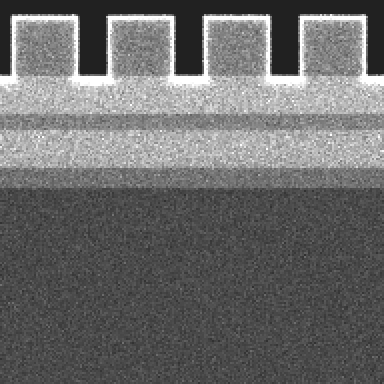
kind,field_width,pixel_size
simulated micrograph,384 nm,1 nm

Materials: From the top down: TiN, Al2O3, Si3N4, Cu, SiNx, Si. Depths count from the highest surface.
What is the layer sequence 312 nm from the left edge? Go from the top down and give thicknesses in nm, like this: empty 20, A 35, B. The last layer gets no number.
TiN 60, Al2O3 38, Si3N4 16, Cu 38, SiNx 20, Si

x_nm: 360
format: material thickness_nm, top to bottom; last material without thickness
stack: TiN 60, Al2O3 38, Si3N4 16, Cu 38, SiNx 20, Si